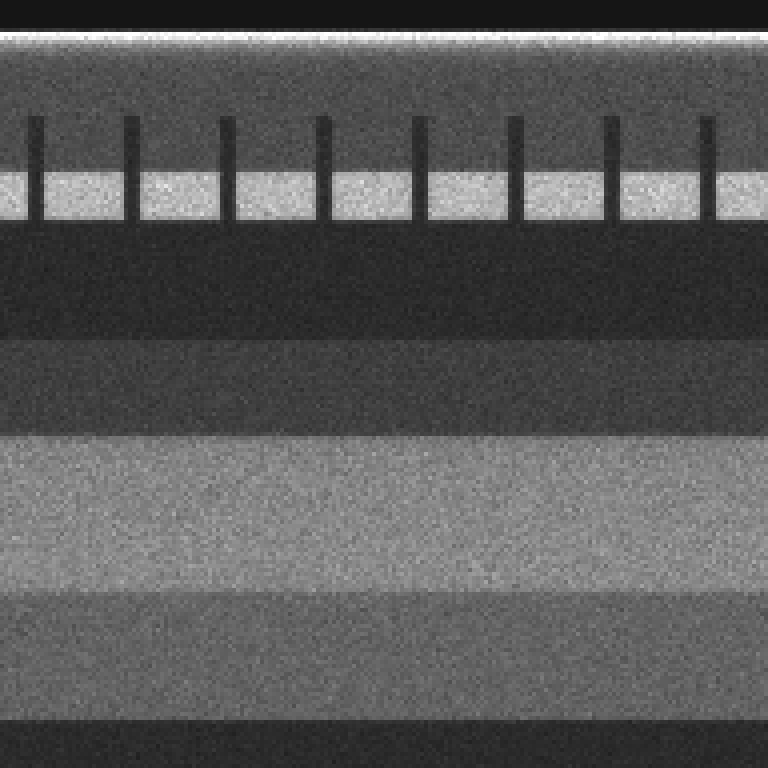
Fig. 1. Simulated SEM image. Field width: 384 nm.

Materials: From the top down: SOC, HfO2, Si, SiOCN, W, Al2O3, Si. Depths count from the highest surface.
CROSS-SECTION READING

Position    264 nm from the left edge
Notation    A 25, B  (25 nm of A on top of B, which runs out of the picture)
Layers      SOC 70, HfO2 24, Si 60, SiOCN 48, W 78, Al2O3 64, Si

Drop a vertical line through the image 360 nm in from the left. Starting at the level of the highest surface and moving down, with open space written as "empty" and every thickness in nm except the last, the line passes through SOC 70, HfO2 24, Si 60, SiOCN 48, W 78, Al2O3 64, Si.